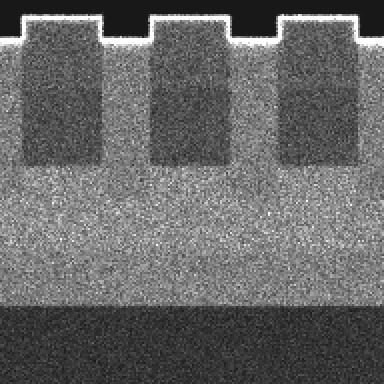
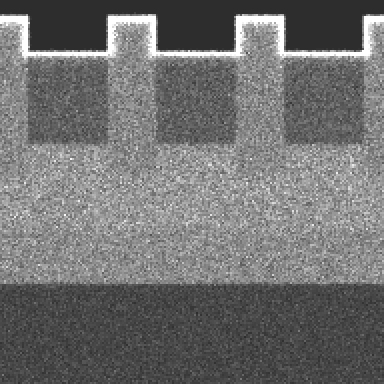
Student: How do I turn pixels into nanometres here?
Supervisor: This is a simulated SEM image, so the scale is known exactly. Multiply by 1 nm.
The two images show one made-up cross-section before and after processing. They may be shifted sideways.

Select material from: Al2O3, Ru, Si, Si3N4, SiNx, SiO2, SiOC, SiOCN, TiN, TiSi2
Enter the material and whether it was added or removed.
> Si3N4 / removed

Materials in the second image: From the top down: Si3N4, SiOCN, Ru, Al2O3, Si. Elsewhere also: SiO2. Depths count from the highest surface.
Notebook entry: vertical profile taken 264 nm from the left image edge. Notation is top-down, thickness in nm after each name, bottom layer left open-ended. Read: SiO2 158, Ru 56, Al2O3 54, Si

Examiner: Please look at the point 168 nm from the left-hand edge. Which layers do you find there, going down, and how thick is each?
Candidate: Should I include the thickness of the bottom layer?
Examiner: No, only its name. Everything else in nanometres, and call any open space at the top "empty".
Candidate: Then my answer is empty 36, Si3N4 14, SiOCN 78, Ru 86, Al2O3 54, Si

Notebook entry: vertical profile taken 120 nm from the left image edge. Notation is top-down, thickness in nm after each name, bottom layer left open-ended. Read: SiO2 158, Ru 56, Al2O3 54, Si